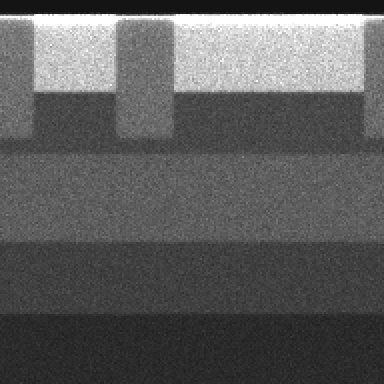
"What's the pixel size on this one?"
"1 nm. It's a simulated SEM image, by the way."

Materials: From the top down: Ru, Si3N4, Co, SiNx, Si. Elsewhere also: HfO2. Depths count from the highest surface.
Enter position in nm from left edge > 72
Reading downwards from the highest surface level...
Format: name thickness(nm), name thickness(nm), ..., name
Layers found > HfO2 76, Si3N4 62, Co 88, SiNx 72, Si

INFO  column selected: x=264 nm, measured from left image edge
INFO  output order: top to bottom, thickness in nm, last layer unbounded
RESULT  HfO2 76, Si3N4 62, Co 88, SiNx 72, Si